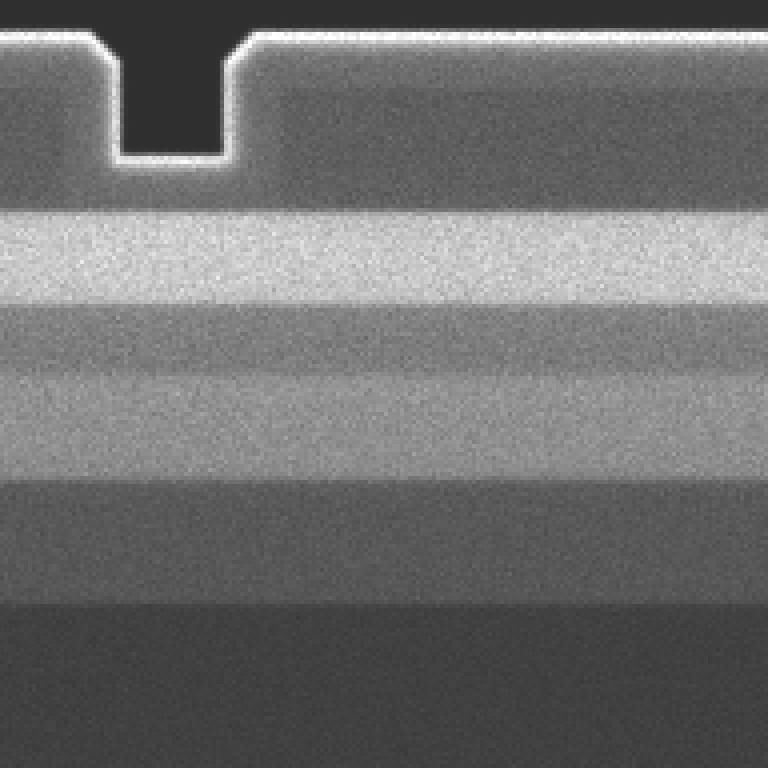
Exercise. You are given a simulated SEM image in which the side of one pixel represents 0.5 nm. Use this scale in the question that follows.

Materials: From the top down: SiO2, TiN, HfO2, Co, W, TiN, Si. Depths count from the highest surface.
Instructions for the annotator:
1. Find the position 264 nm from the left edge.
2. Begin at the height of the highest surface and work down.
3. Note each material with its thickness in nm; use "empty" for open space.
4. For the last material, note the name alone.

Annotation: SiO2 28, TiN 62, HfO2 46, Co 36, W 52, TiN 62, Si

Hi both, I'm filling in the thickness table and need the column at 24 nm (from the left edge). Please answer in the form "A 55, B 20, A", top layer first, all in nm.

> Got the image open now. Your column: SiO2 28, TiN 62, HfO2 46, Co 36, W 52, TiN 62, Si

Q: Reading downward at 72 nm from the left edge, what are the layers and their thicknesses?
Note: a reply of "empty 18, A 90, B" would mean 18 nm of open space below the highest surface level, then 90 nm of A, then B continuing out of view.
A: empty 62, SiO2 28, HfO2 46, Co 36, W 52, TiN 62, Si